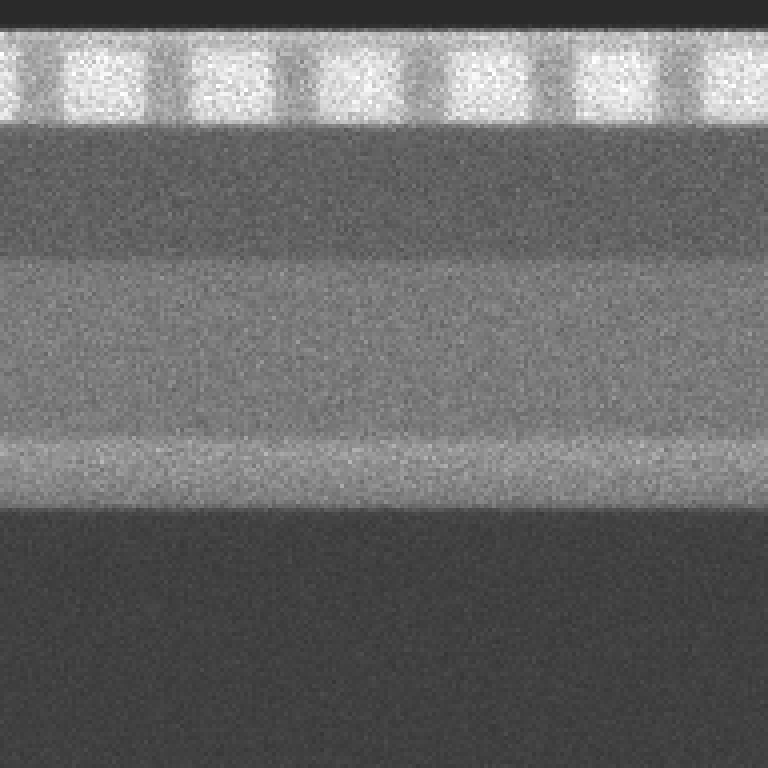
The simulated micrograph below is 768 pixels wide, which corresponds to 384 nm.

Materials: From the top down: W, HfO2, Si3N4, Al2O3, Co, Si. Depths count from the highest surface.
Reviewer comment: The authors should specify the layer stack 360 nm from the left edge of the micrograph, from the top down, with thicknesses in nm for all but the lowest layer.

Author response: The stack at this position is W 10, HfO2 36, Si3N4 68, Al2O3 90, Co 34, Si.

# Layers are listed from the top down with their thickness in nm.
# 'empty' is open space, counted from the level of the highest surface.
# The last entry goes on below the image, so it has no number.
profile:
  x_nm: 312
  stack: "W 10, HfO2 36, Si3N4 68, Al2O3 90, Co 34, Si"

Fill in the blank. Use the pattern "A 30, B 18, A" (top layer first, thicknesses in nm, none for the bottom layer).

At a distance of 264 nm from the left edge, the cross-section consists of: W 46, Si3N4 68, Al2O3 90, Co 34, Si